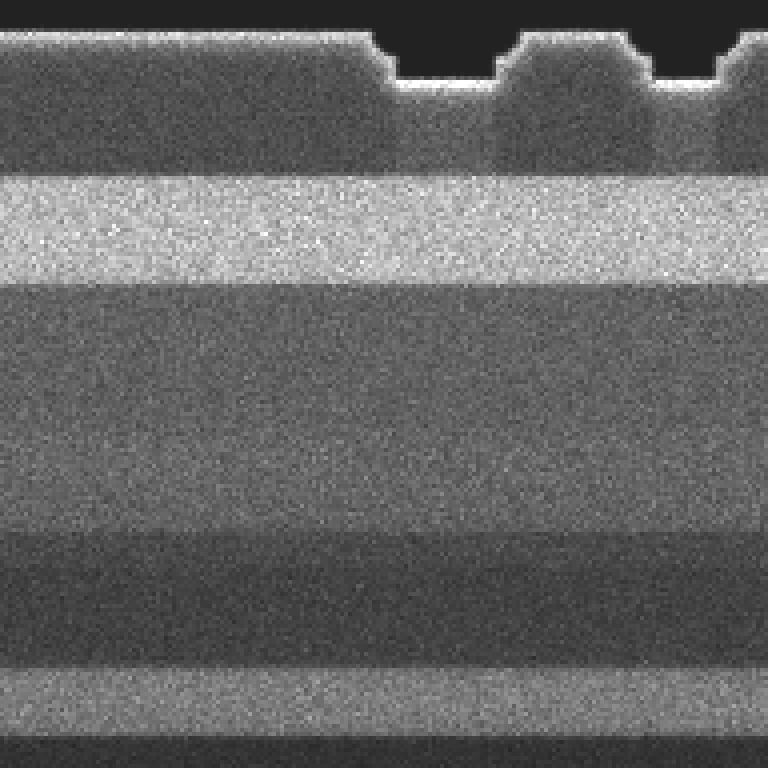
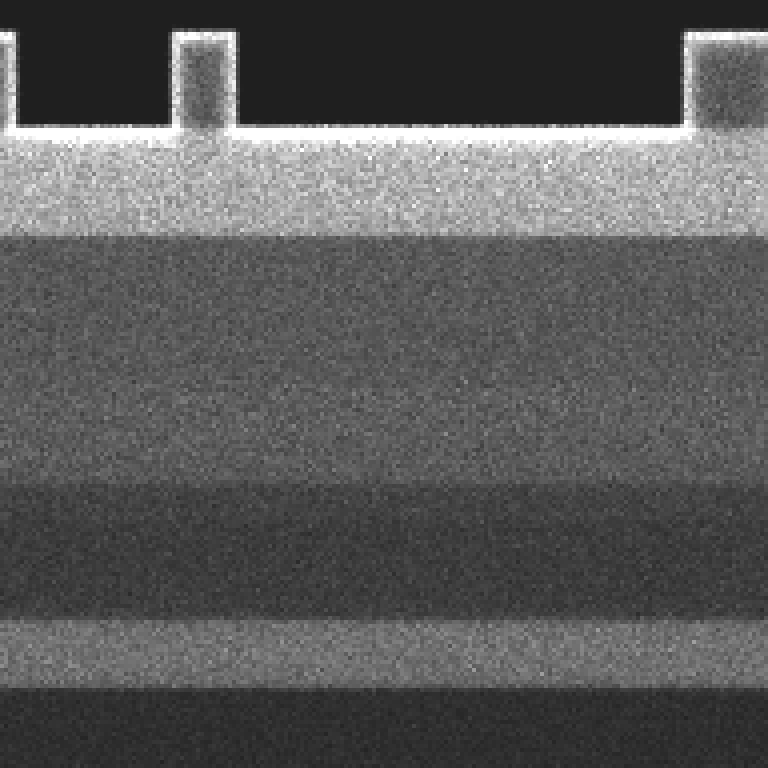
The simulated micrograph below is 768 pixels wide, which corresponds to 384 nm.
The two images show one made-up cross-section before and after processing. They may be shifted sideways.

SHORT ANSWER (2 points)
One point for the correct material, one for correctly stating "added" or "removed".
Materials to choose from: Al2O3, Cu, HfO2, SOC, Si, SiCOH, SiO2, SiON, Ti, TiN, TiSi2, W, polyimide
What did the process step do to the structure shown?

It removed SOC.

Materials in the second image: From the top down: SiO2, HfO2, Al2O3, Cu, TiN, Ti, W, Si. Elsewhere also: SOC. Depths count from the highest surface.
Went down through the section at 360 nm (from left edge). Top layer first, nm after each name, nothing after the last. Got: SiO2 48, HfO2 54, Al2O3 74, Cu 50, TiN 18, Ti 50, W 34, Si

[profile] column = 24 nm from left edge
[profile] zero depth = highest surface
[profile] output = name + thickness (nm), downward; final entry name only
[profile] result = empty 48, HfO2 54, Al2O3 74, Cu 50, TiN 18, Ti 50, W 34, Si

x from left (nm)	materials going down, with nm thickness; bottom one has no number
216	empty 48, HfO2 54, Al2O3 74, Cu 50, TiN 18, Ti 50, W 34, Si